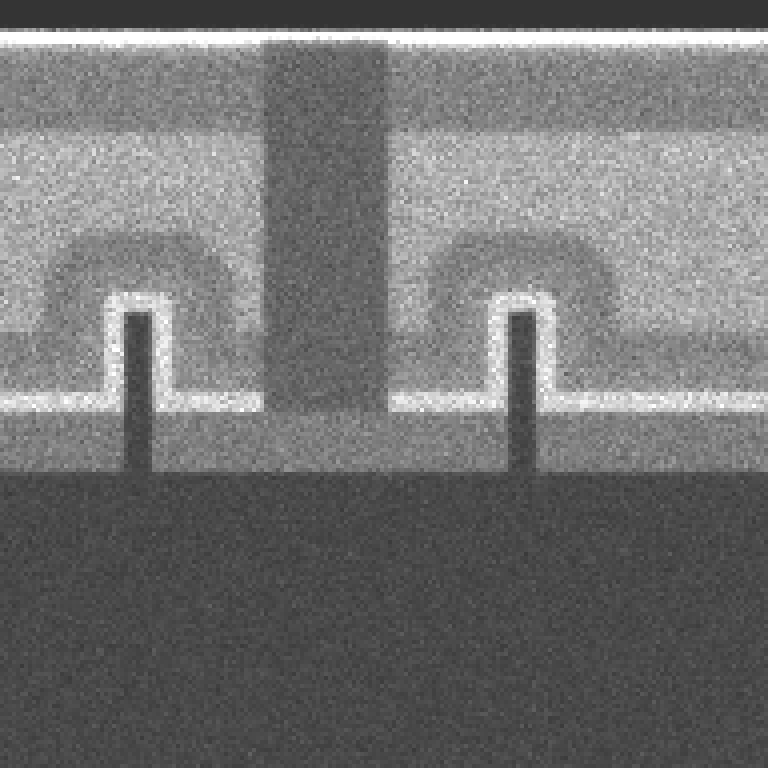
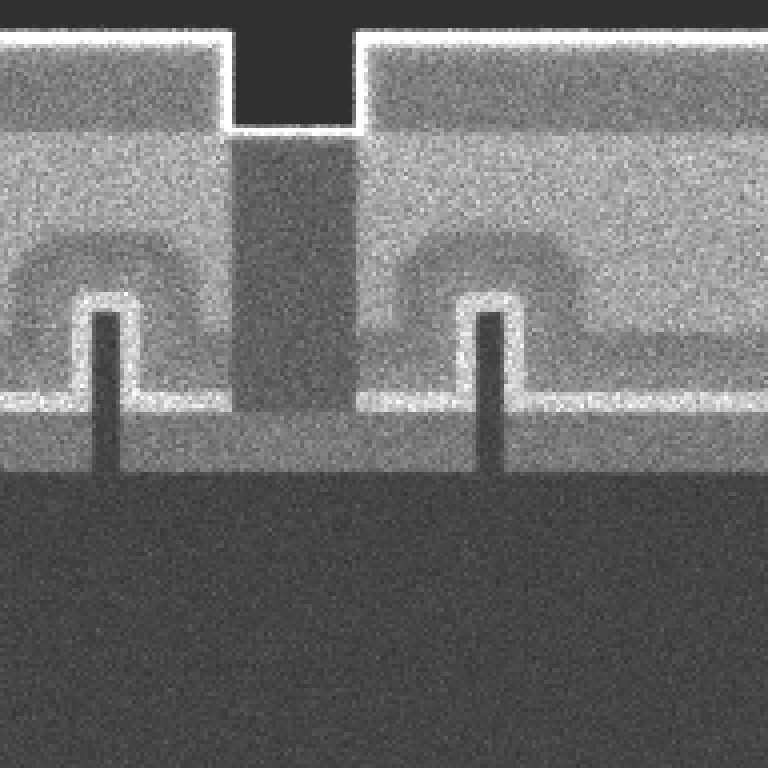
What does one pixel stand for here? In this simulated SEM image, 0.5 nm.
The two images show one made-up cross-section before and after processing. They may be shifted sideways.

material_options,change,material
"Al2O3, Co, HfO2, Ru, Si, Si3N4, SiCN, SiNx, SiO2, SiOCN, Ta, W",removed,Si3N4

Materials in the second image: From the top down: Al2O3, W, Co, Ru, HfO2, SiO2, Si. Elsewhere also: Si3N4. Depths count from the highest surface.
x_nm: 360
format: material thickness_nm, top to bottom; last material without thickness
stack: Al2O3 50, W 100, Co 16, Ru 14, HfO2 10, SiO2 30, Si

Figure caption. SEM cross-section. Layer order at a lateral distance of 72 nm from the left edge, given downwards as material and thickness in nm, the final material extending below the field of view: Al2O3 50, W 50, Co 16, Ru 64, HfO2 10, SiO2 30, Si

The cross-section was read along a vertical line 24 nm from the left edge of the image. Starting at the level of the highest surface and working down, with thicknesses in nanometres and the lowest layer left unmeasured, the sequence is Al2O3 50, W 50, Co 24, Ru 56, HfO2 10, SiO2 30, Si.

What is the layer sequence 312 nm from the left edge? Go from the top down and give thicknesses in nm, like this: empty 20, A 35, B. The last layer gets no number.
Al2O3 50, W 100, Co 16, Ru 14, HfO2 10, SiO2 30, Si